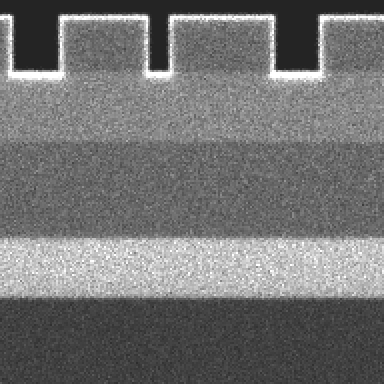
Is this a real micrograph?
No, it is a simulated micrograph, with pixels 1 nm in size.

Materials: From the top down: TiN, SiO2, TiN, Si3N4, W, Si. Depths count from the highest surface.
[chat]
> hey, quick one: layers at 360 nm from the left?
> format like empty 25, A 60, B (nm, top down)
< TiN 56, SiO2 70, TiN 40, Si3N4 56, W 60, Si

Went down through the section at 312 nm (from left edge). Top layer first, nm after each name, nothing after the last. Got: empty 56, SiO2 70, TiN 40, Si3N4 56, W 60, Si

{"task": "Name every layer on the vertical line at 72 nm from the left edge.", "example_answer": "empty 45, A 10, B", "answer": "TiN 56, SiO2 70, TiN 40, Si3N4 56, W 60, Si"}